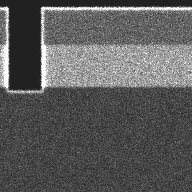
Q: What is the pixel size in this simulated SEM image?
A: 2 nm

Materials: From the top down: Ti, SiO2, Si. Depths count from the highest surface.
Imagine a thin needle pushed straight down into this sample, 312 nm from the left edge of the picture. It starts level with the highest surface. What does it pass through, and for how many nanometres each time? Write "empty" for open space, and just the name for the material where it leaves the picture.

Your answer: Ti 74, SiO2 84, Si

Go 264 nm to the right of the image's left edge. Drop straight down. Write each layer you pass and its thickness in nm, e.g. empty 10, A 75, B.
Ti 74, SiO2 84, Si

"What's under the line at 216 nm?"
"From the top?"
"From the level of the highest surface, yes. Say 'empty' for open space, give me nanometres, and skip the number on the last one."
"Ti 74, SiO2 84, Si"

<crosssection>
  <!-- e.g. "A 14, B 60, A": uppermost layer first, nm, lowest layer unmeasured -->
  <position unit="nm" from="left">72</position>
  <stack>empty 166, Si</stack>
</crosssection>